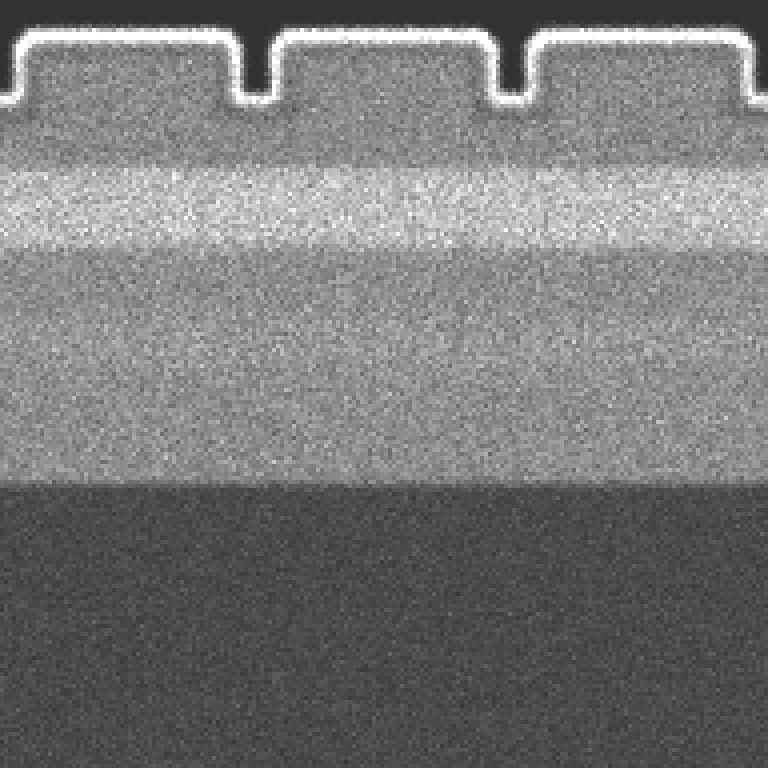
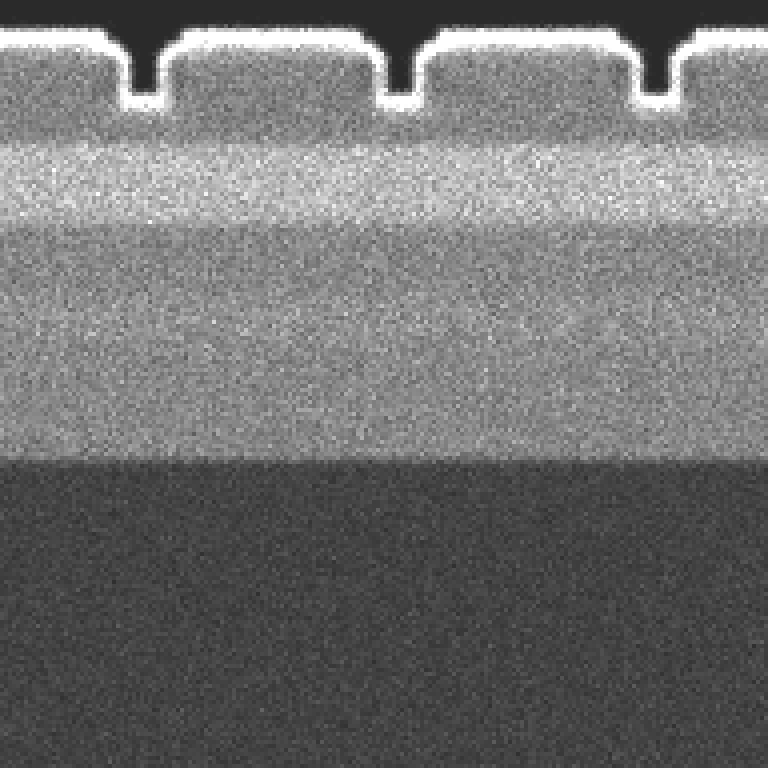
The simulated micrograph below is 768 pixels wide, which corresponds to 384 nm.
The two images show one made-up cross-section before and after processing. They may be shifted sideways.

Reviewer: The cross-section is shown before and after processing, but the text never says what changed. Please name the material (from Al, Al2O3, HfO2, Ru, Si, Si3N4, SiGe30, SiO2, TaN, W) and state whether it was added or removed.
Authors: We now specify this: Si3N4, removed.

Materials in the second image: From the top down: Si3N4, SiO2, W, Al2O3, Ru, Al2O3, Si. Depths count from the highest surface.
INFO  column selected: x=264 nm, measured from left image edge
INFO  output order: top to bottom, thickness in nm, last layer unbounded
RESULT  SiO2 56, W 40, Al2O3 34, Ru 26, Al2O3 58, Si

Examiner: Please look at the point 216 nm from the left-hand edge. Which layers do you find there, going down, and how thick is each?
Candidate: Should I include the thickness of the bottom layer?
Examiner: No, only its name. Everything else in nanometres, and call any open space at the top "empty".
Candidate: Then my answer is empty 6, Si3N4 26, SiO2 24, W 40, Al2O3 34, Ru 26, Al2O3 58, Si